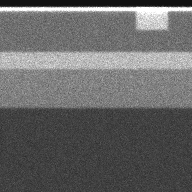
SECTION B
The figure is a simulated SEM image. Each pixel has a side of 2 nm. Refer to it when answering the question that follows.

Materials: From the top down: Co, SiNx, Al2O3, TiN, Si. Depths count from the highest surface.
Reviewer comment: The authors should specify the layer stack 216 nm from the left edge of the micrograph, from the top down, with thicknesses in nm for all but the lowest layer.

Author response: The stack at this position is SiNx 88, Al2O3 34, TiN 78, Si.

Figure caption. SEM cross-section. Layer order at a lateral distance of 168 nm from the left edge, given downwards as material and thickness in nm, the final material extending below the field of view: SiNx 88, Al2O3 34, TiN 78, Si